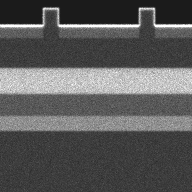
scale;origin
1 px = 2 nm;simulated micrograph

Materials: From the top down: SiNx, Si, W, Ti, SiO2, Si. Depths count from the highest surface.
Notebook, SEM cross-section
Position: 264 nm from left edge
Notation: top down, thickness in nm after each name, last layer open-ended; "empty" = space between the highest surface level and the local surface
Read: empty 34, SiNx 26, Si 60, W 52, Ti 44, SiO2 30, Si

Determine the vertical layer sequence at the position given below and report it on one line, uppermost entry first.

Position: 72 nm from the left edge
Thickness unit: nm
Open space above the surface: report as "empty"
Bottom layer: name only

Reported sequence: empty 34, SiNx 26, Si 60, W 52, Ti 44, SiO2 30, Si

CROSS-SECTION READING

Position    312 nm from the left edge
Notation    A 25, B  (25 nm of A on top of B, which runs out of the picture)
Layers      empty 34, SiNx 26, Si 60, W 52, Ti 44, SiO2 30, Si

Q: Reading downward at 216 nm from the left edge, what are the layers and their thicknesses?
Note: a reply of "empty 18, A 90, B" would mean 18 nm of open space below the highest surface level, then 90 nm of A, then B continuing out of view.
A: empty 34, SiNx 26, Si 60, W 52, Ti 44, SiO2 30, Si